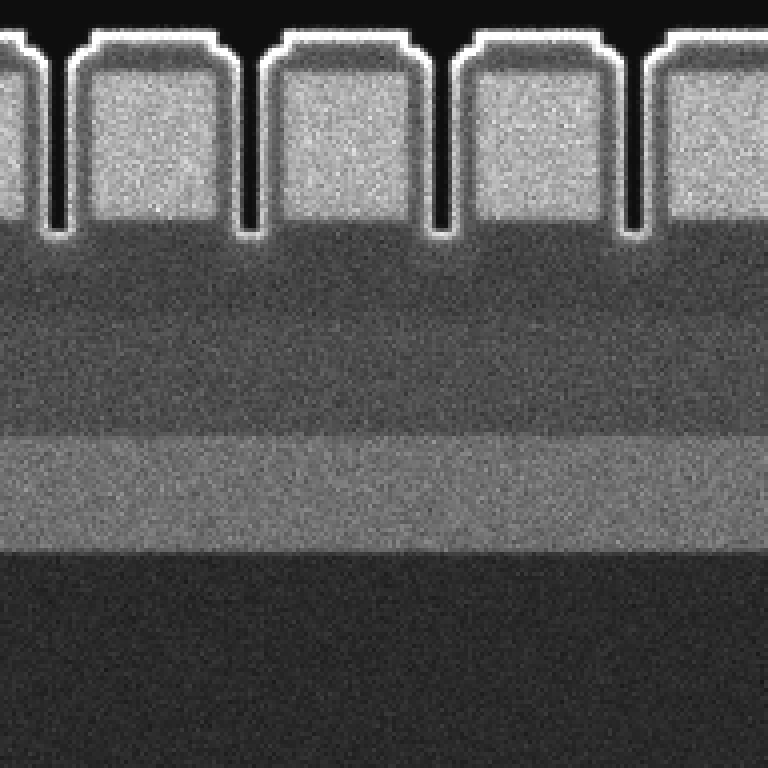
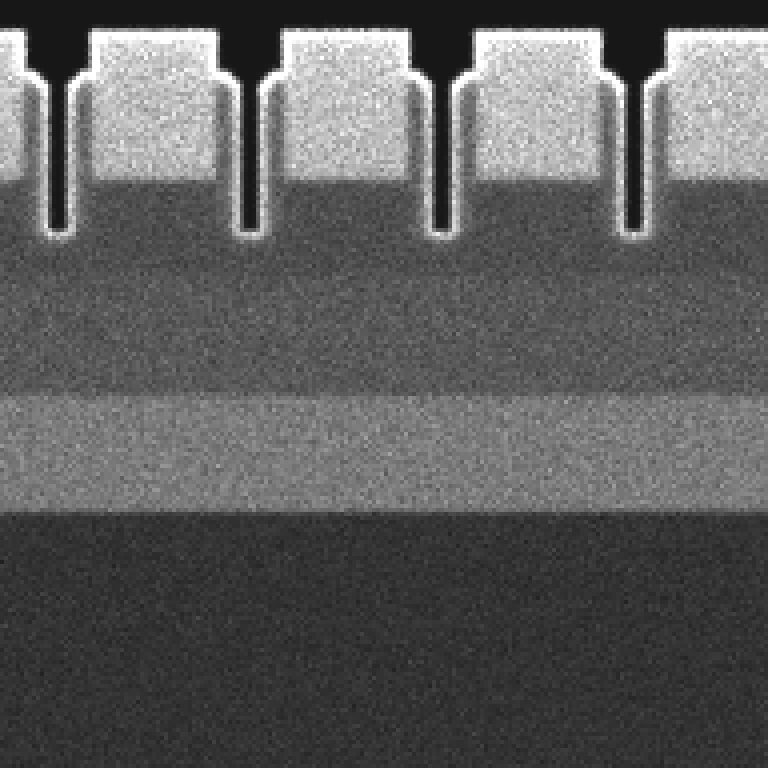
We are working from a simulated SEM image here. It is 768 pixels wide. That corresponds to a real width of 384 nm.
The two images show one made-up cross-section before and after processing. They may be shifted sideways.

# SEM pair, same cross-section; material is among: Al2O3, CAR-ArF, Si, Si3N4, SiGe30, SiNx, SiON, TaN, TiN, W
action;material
removed;Si3N4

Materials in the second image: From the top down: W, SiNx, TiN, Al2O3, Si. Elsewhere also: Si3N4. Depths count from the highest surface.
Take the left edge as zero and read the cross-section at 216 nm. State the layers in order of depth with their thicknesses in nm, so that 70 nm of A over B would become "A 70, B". empty 100, SiNx 22, TiN 60, Al2O3 58, Si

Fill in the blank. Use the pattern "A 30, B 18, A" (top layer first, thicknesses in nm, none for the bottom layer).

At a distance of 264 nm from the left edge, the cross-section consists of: W 74, SiNx 48, TiN 60, Al2O3 58, Si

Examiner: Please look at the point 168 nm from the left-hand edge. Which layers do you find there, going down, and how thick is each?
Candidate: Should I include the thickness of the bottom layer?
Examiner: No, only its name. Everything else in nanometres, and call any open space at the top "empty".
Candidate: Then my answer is W 74, SiNx 48, TiN 60, Al2O3 58, Si